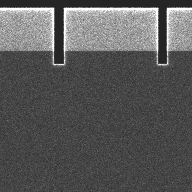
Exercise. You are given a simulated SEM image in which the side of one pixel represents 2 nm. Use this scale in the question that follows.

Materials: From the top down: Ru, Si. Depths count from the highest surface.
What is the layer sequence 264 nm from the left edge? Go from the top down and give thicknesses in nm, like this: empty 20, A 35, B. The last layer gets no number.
Ru 86, Si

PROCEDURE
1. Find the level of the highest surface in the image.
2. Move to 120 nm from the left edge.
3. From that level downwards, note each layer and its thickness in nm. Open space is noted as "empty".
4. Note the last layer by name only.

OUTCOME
empty 112, Si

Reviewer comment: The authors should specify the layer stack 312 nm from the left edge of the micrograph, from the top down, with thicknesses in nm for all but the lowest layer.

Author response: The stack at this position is Ru 86, Si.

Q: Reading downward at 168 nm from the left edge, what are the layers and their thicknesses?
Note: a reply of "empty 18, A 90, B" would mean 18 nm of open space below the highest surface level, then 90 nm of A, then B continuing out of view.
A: Ru 86, Si